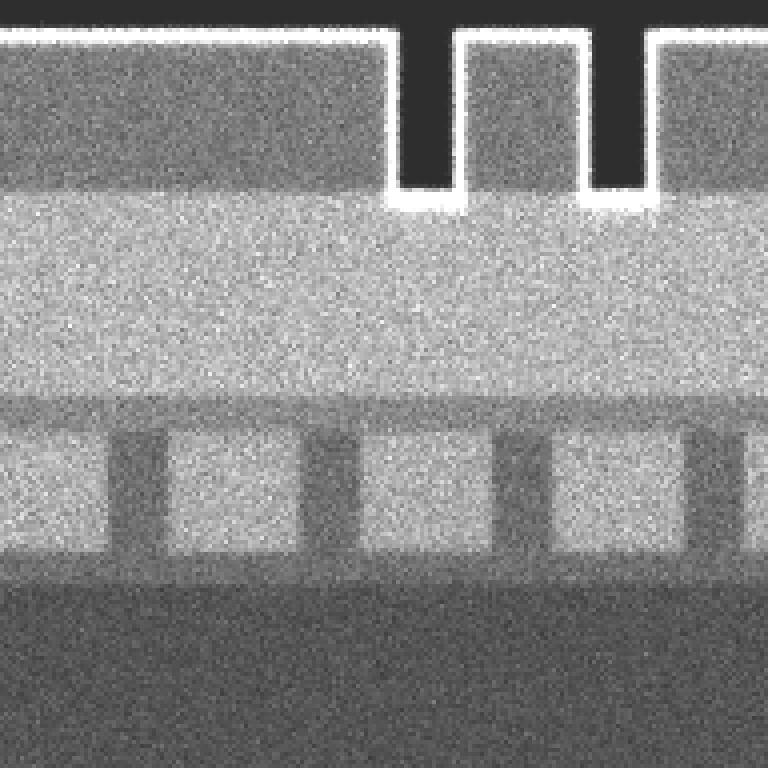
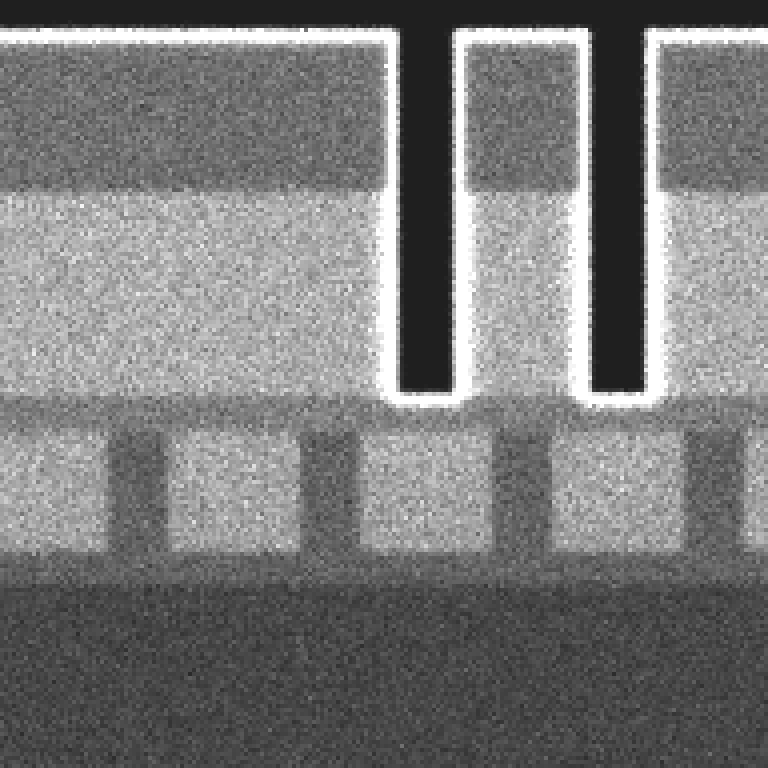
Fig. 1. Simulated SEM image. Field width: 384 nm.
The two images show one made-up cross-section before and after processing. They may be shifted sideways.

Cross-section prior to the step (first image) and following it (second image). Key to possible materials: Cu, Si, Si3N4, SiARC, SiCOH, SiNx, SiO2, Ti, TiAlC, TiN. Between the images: SiO2 was removed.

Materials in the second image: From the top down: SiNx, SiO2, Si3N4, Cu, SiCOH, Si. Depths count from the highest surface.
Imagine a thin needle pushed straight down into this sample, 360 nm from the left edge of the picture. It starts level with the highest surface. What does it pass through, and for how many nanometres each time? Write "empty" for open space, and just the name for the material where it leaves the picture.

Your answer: SiNx 80, SiO2 102, Si3N4 18, SiCOH 76, Si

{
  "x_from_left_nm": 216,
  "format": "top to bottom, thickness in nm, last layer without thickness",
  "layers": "empty 182, Si3N4 18, Cu 60, SiCOH 16, Si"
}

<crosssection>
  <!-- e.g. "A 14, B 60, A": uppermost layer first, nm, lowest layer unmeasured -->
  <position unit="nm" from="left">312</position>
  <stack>empty 182, Si3N4 18, Cu 60, SiCOH 16, Si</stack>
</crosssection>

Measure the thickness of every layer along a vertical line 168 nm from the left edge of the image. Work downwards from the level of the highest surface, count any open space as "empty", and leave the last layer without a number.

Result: SiNx 80, SiO2 102, Si3N4 18, SiCOH 76, Si